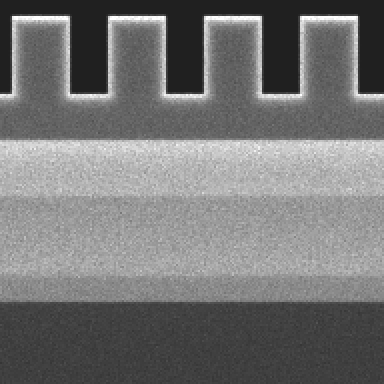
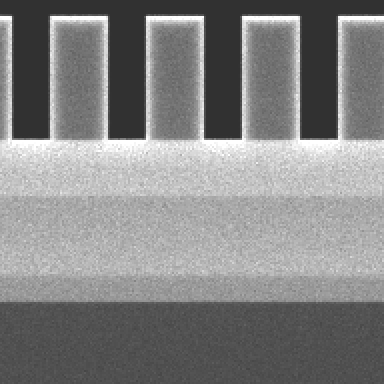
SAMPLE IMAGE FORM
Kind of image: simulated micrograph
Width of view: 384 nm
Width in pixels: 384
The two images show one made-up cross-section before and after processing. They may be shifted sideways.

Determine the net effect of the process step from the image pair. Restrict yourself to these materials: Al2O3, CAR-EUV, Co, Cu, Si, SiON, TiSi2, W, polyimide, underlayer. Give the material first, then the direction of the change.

underlayer: removed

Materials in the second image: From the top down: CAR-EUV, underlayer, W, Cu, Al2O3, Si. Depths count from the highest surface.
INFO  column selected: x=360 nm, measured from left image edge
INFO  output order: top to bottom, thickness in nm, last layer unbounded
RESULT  CAR-EUV 78, underlayer 46, W 56, Cu 80, Al2O3 26, Si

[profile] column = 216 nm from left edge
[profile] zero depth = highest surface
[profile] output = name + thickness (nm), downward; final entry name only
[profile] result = empty 124, W 56, Cu 80, Al2O3 26, Si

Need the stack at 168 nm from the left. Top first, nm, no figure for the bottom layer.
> CAR-EUV 78, underlayer 46, W 56, Cu 80, Al2O3 26, Si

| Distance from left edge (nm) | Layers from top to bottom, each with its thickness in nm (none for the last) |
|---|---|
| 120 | empty 124, W 56, Cu 80, Al2O3 26, Si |